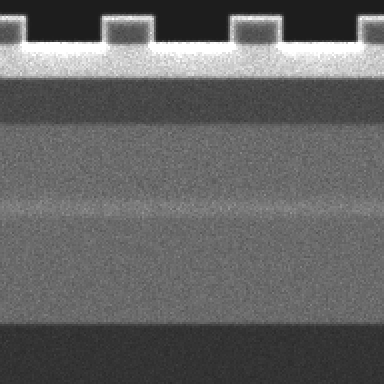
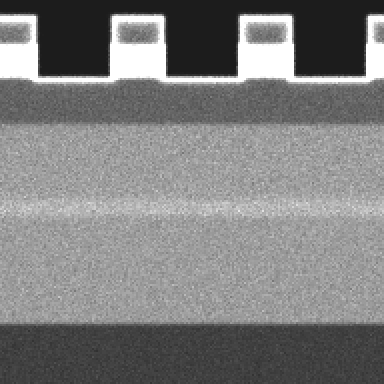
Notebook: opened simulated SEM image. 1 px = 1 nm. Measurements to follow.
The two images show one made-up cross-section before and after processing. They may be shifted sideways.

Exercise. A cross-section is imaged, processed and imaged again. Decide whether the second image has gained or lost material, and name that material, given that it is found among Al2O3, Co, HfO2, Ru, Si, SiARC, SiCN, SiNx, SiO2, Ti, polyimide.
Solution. removed: HfO2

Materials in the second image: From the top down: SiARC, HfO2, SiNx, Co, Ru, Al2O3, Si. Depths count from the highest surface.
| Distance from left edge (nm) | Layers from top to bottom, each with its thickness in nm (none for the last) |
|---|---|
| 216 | empty 62, SiNx 46, Co 76, Ru 16, Al2O3 108, Si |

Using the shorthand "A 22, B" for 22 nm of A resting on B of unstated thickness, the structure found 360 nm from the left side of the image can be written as empty 62, SiNx 46, Co 76, Ru 16, Al2O3 108, Si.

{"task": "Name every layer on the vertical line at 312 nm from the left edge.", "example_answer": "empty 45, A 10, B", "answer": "empty 62, SiNx 46, Co 76, Ru 16, Al2O3 108, Si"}